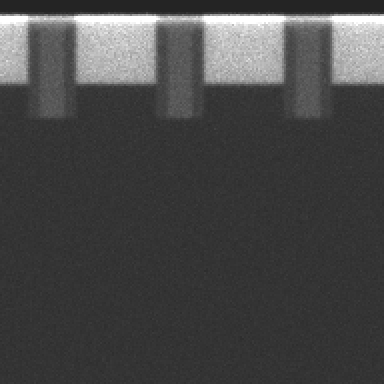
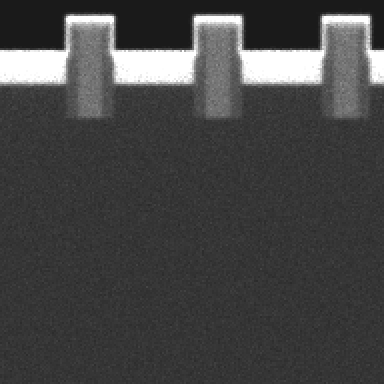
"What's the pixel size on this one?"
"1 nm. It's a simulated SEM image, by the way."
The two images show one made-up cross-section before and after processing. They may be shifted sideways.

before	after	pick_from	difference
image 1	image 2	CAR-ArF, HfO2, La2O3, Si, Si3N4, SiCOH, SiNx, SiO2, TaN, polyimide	HfO2 removed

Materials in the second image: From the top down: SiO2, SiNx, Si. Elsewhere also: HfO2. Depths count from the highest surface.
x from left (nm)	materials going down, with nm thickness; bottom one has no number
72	SiO2 10, SiNx 92, Si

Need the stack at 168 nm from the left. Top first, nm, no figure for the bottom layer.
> empty 36, HfO2 32, Si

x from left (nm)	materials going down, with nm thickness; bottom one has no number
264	empty 36, HfO2 32, Si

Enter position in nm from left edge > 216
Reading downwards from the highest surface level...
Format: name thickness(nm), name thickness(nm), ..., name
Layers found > SiO2 102, Si